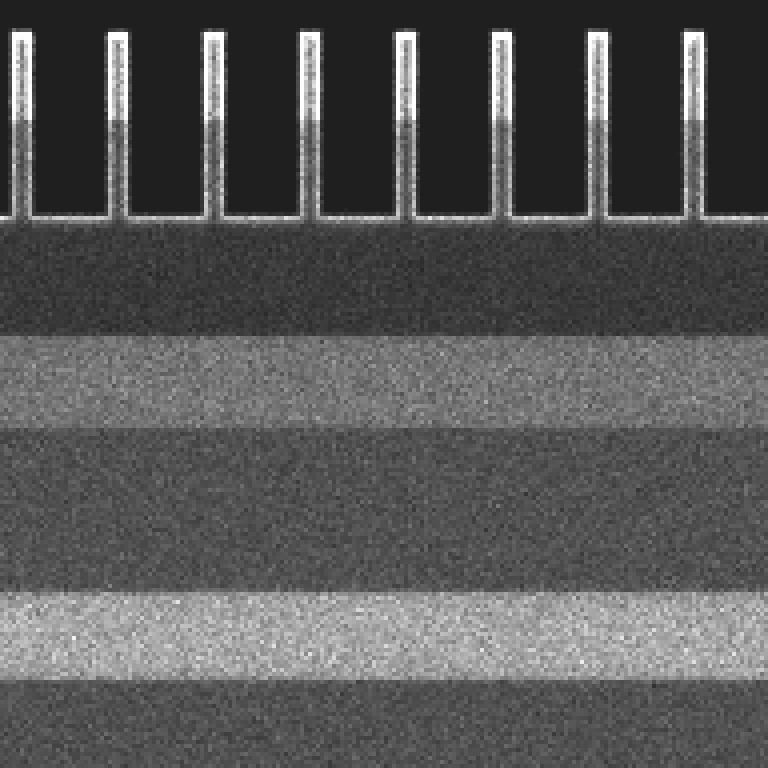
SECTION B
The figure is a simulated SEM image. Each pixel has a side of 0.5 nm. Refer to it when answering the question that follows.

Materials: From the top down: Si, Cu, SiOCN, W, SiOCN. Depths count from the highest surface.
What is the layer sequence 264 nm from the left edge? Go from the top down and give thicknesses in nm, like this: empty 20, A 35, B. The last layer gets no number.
empty 92, Si 60, Cu 46, SiOCN 82, W 44, SiOCN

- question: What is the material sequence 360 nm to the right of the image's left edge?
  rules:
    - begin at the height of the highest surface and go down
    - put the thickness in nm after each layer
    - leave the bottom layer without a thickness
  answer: empty 92, Si 60, Cu 46, SiOCN 82, W 44, SiOCN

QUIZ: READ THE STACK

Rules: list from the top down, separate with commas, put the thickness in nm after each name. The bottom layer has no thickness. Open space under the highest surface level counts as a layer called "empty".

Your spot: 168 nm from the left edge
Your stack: empty 92, Si 60, Cu 46, SiOCN 82, W 44, SiOCN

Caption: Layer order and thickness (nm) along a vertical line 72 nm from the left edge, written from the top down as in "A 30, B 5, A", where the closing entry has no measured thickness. empty 92, Si 60, Cu 46, SiOCN 82, W 44, SiOCN